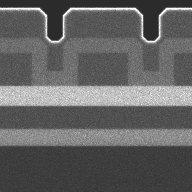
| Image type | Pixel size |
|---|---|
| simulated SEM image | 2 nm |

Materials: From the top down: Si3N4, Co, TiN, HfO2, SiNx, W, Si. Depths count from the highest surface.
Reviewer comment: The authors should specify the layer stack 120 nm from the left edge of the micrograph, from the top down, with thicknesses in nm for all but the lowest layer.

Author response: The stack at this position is empty 62, Si3N4 64, Co 30, HfO2 40, SiNx 46, W 34, Si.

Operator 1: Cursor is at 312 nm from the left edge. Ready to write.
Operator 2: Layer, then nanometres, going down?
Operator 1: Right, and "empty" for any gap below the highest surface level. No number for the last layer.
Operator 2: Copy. empty 62, Si3N4 64, Co 30, HfO2 40, SiNx 46, W 34, Si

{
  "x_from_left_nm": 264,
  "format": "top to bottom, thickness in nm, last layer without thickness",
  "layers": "Si3N4 60, Co 96, HfO2 40, SiNx 46, W 34, Si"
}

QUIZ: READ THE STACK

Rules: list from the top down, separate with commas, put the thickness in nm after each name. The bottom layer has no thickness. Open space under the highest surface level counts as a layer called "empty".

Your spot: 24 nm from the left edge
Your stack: Si3N4 60, Co 30, TiN 66, HfO2 40, SiNx 46, W 34, Si